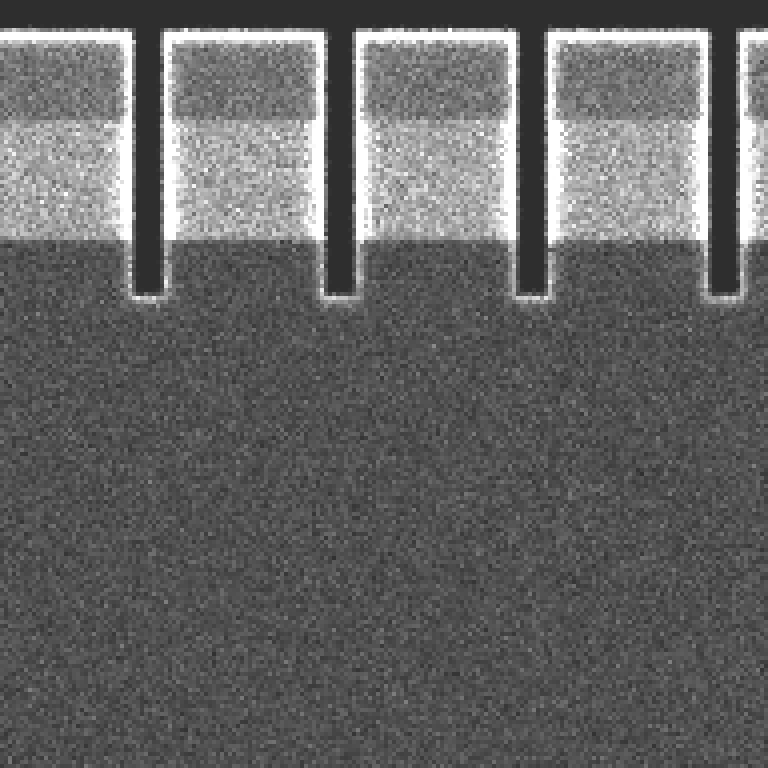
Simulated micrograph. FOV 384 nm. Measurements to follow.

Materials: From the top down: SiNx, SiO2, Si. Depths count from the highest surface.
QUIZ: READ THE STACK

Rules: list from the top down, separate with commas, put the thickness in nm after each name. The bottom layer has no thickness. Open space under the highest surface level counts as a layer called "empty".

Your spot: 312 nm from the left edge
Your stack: SiNx 44, SiO2 60, Si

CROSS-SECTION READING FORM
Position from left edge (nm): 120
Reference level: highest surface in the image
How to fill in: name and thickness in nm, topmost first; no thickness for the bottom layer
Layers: SiNx 44, SiO2 60, Si